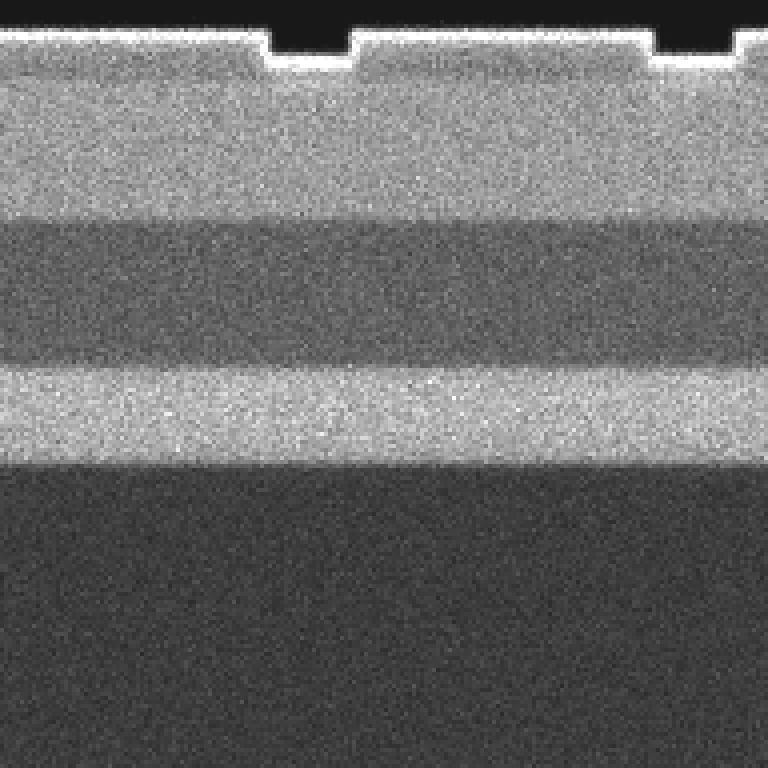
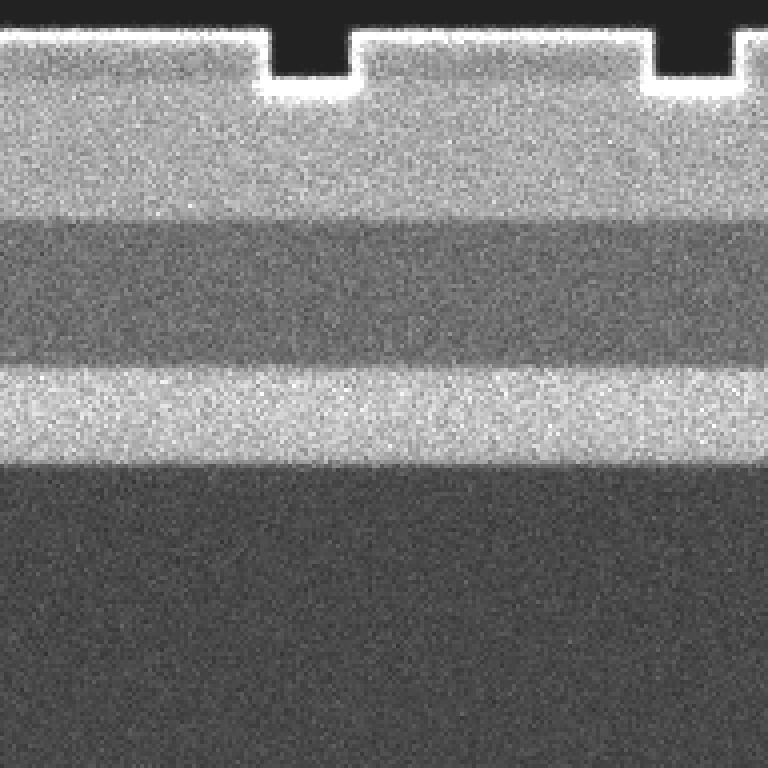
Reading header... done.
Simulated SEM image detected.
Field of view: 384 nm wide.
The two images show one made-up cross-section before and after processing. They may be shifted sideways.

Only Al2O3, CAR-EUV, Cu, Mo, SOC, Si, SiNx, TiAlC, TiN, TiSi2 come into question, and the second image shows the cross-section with SOC removed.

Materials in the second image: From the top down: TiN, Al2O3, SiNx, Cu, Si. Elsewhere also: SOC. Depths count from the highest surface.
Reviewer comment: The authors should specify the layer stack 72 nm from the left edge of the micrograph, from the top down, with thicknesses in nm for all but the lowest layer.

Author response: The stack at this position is TiN 24, Al2O3 70, SiNx 74, Cu 48, Si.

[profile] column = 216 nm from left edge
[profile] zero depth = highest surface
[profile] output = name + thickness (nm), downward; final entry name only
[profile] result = TiN 24, Al2O3 70, SiNx 74, Cu 48, Si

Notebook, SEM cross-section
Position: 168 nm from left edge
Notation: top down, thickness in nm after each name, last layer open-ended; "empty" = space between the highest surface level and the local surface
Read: empty 24, Al2O3 70, SiNx 74, Cu 48, Si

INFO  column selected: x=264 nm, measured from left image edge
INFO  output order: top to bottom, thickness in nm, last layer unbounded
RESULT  TiN 24, Al2O3 70, SiNx 74, Cu 48, Si